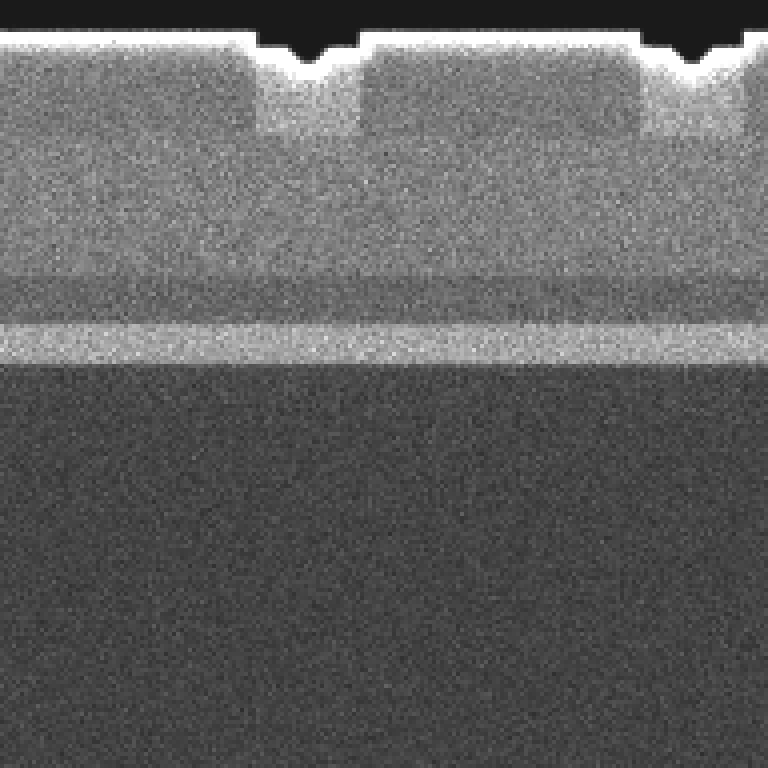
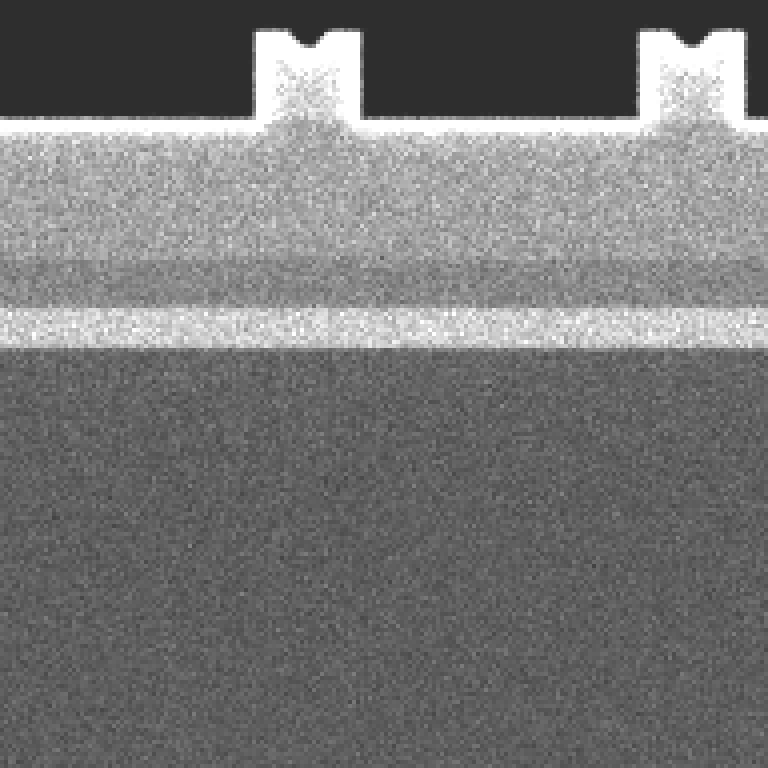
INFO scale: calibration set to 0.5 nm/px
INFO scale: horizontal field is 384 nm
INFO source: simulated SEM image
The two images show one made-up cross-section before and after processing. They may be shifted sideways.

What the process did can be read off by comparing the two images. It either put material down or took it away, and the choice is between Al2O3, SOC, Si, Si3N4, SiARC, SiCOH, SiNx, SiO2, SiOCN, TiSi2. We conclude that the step removed SOC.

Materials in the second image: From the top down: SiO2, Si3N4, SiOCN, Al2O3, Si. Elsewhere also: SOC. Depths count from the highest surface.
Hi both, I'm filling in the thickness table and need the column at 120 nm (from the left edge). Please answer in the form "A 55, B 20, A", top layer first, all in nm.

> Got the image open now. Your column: empty 44, Si3N4 70, SiOCN 24, Al2O3 20, Si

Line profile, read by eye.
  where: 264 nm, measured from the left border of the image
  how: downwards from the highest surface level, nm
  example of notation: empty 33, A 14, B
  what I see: empty 44, Si3N4 70, SiOCN 24, Al2O3 20, Si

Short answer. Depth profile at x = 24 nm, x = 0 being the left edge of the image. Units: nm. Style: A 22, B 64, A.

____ empty 44, Si3N4 70, SiOCN 24, Al2O3 20, Si